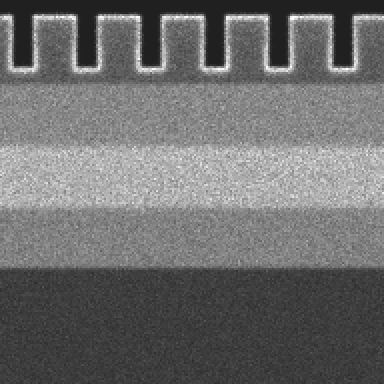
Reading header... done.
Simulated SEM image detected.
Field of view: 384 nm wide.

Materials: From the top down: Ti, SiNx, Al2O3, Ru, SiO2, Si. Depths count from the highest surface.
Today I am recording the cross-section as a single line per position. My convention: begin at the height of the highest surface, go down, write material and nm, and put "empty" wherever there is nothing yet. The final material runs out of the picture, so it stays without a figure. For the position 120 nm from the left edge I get Ti 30, SiNx 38, Al2O3 62, Ru 62, SiO2 60, Si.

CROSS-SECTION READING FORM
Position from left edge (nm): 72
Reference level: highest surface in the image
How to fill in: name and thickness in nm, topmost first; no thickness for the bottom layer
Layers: Ti 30, SiNx 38, Al2O3 62, Ru 62, SiO2 60, Si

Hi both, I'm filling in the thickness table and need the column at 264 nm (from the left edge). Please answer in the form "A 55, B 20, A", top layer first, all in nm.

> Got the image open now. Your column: Ti 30, SiNx 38, Al2O3 62, Ru 62, SiO2 60, Si